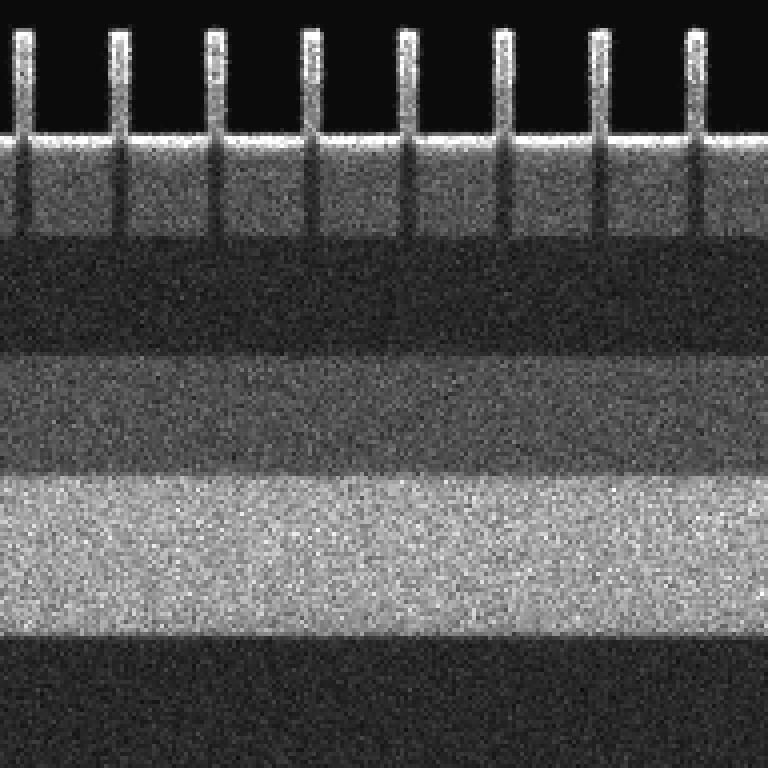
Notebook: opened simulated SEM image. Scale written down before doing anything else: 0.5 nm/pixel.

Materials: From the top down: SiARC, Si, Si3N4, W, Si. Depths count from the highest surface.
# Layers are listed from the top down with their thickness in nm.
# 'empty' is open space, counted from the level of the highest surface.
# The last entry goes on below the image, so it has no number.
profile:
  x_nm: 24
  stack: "empty 52, SiARC 50, Si 60, Si3N4 60, W 80, Si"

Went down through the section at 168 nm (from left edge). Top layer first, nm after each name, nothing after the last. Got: empty 52, SiARC 50, Si 60, Si3N4 60, W 80, Si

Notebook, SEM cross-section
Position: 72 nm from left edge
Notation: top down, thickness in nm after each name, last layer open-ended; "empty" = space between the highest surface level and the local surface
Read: empty 52, SiARC 50, Si 60, Si3N4 60, W 80, Si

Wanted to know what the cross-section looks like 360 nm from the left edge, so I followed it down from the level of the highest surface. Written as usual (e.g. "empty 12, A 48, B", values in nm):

empty 52, SiARC 50, Si 60, Si3N4 60, W 80, Si